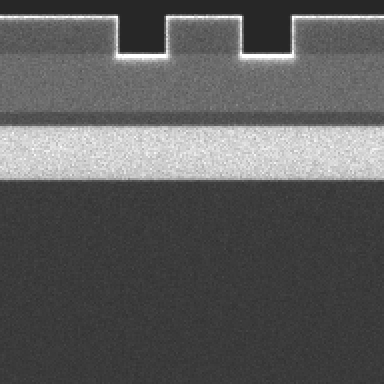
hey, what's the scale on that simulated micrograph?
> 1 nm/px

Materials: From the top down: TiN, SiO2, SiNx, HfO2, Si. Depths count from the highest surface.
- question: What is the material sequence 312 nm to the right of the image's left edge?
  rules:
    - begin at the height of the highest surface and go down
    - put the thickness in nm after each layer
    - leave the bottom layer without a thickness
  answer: TiN 38, SiO2 58, SiNx 14, HfO2 54, Si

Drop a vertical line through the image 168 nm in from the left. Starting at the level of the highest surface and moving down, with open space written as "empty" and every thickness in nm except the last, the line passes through TiN 38, SiO2 58, SiNx 14, HfO2 54, Si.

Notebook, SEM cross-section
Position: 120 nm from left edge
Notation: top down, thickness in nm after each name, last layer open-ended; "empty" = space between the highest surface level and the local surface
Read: empty 38, SiO2 58, SiNx 14, HfO2 54, Si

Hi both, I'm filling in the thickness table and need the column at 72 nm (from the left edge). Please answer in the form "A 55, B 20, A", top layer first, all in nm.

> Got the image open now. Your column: TiN 38, SiO2 58, SiNx 14, HfO2 54, Si